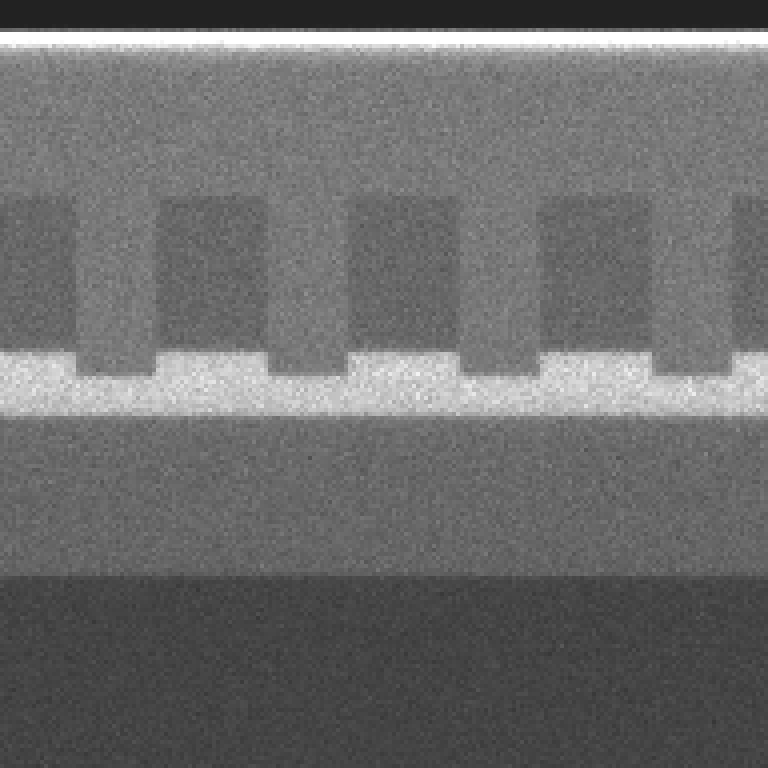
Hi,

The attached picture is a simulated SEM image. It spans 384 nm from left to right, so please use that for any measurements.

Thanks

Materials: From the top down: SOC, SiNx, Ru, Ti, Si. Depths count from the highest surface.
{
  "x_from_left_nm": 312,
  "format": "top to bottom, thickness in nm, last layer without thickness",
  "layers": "SOC 82, SiNx 78, Ru 32, Ti 80, Si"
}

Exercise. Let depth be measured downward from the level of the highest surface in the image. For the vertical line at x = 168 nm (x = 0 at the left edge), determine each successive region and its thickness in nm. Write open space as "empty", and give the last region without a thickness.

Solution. SOC 172, Ru 20, Ti 80, Si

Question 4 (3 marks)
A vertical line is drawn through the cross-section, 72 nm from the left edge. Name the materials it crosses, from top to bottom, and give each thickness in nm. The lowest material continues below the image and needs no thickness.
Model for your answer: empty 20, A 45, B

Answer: SOC 172, Ru 20, Ti 80, Si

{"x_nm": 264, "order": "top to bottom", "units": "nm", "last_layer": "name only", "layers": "SOC 172, Ru 20, Ti 80, Si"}